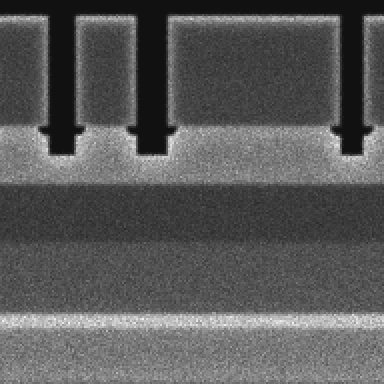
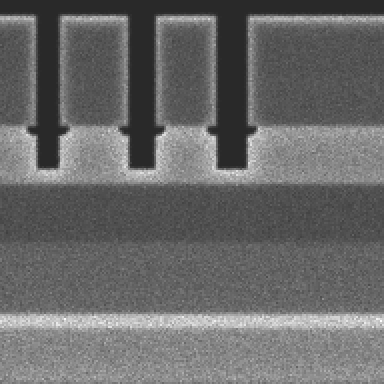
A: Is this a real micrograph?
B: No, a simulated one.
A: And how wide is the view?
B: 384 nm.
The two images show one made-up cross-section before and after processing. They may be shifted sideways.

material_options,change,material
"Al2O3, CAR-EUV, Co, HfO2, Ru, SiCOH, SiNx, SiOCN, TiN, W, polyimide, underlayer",removed,W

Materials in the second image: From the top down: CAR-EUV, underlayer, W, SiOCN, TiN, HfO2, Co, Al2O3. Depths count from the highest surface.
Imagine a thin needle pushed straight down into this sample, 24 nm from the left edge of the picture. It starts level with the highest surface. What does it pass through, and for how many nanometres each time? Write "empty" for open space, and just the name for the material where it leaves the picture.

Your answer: CAR-EUV 60, underlayer 50, W 58, SiOCN 58, TiN 72, HfO2 14, Co 54, Al2O3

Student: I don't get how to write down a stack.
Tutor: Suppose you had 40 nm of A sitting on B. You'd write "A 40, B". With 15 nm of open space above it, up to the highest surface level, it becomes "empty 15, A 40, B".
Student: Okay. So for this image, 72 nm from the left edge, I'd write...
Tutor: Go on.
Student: CAR-EUV 60, underlayer 50, W 58, SiOCN 58, TiN 72, HfO2 14, Co 54, Al2O3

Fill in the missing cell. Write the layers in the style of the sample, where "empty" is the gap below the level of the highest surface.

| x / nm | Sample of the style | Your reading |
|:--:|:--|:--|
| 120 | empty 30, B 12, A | CAR-EUV 60, underlayer 50, empty 8, W 50, SiOCN 58, TiN 72, HfO2 14, Co 54, Al2O3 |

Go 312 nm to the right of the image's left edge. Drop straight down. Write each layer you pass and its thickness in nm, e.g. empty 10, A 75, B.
CAR-EUV 60, underlayer 50, W 58, SiOCN 58, TiN 72, HfO2 14, Co 54, Al2O3